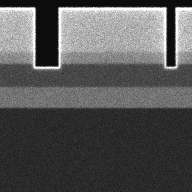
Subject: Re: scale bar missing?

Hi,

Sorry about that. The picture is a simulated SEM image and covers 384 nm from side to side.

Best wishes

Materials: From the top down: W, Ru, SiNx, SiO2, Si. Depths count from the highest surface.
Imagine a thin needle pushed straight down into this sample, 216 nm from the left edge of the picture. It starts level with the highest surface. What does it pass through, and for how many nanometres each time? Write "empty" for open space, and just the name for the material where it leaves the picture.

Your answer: W 88, Ru 24, SiNx 46, SiO2 42, Si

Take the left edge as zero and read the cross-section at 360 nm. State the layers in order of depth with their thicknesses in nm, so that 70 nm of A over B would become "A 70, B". W 88, Ru 24, SiNx 46, SiO2 42, Si